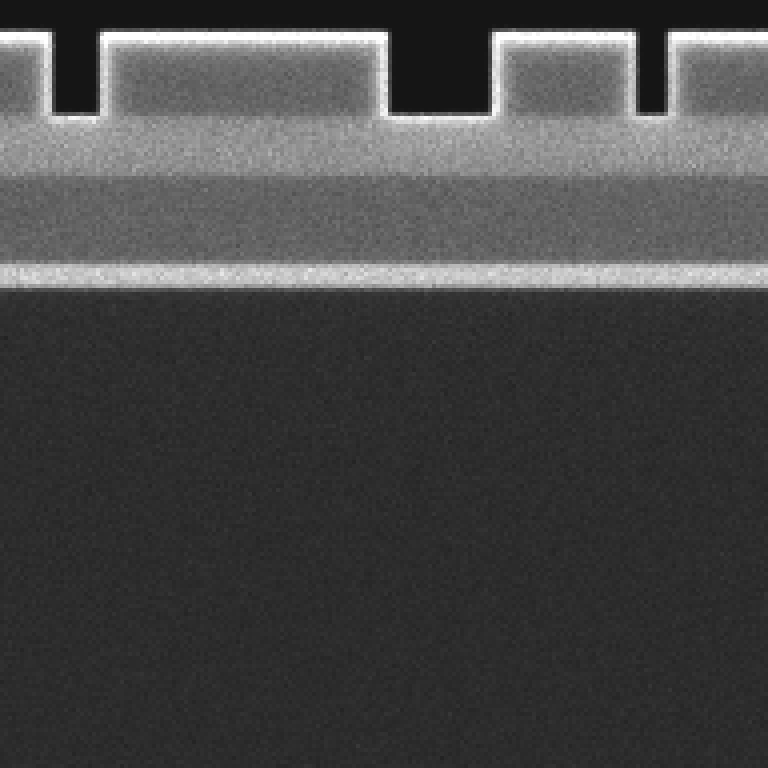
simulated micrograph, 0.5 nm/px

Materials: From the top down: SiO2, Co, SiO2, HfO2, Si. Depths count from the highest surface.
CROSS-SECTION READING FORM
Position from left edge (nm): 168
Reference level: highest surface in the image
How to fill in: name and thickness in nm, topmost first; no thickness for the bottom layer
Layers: SiO2 42, Co 30, SiO2 44, HfO2 12, Si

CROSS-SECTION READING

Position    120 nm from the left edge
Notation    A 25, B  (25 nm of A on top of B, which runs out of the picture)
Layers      SiO2 42, Co 30, SiO2 44, HfO2 12, Si